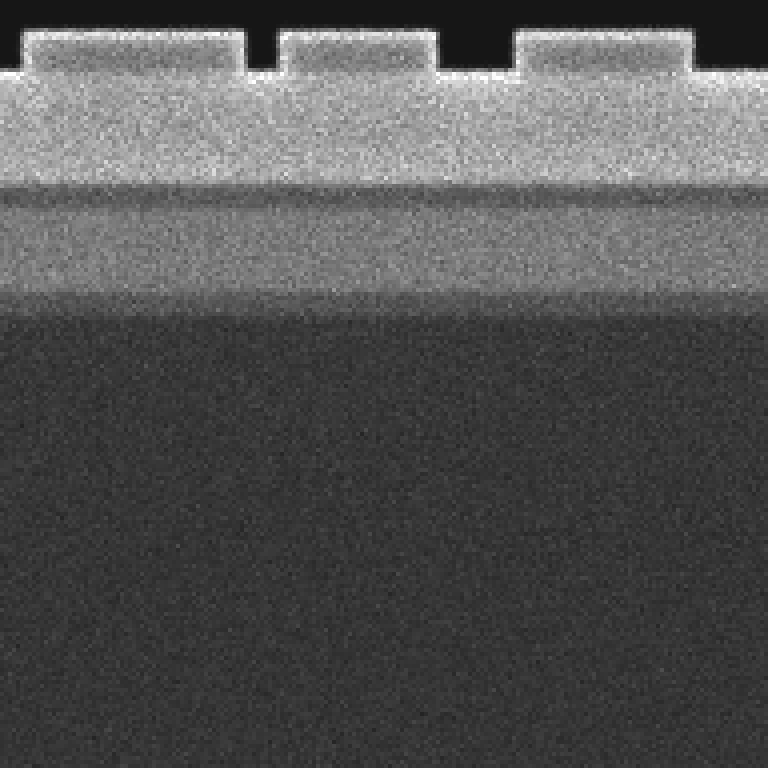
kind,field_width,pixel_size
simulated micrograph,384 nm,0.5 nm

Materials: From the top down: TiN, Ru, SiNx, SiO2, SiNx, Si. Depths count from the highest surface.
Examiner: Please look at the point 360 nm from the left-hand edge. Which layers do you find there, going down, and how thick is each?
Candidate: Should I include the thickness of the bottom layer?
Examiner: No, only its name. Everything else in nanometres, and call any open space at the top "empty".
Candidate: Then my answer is empty 20, Ru 56, SiNx 12, SiO2 42, SiNx 12, Si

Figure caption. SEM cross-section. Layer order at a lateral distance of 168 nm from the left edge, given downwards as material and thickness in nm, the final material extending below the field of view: TiN 20, Ru 56, SiNx 12, SiO2 42, SiNx 12, Si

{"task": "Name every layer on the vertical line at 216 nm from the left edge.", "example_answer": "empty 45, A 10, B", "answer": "TiN 20, Ru 56, SiNx 12, SiO2 42, SiNx 12, Si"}